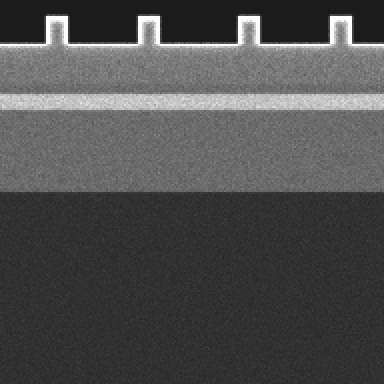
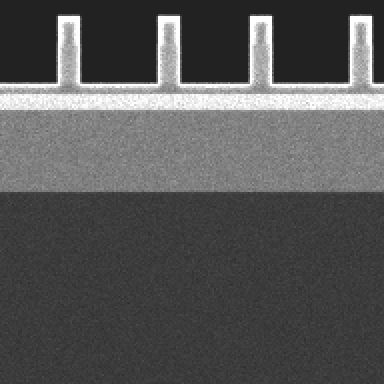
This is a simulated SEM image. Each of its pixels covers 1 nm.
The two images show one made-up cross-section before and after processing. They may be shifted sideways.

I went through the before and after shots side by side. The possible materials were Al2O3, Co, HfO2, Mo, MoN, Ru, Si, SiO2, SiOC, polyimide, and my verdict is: removed, Ru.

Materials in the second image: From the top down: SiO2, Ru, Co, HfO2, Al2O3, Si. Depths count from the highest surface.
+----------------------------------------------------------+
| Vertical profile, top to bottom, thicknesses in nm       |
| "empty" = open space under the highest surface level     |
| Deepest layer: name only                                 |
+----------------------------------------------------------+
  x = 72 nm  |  SiO2 28, Ru 40, Co 10, HfO2 16, Al2O3 82, Si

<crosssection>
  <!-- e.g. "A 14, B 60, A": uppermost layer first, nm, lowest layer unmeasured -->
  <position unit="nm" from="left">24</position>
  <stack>empty 68, Co 10, HfO2 16, Al2O3 82, Si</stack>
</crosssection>